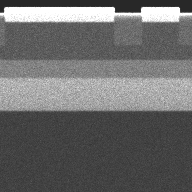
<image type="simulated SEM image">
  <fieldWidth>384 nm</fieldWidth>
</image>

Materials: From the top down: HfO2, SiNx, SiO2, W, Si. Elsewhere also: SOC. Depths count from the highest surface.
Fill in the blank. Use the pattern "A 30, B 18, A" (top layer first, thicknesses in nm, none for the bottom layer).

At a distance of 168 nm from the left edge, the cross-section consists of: HfO2 28, SiNx 76, SiO2 36, W 66, Si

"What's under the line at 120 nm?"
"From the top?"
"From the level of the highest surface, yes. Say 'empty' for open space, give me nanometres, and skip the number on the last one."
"HfO2 28, SiNx 76, SiO2 36, W 66, Si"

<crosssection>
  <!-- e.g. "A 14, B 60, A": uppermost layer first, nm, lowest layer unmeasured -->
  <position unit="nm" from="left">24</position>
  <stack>HfO2 28, SiNx 76, SiO2 36, W 66, Si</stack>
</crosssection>